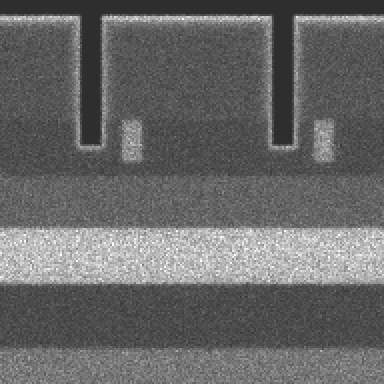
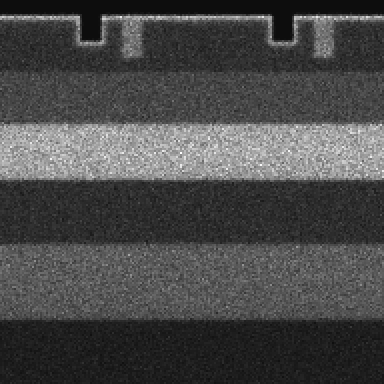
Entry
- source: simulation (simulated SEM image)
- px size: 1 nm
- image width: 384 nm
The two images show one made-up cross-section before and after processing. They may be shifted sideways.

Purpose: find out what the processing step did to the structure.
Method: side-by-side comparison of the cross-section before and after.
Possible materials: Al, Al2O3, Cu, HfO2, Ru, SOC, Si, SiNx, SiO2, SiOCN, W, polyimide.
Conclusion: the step removed SOC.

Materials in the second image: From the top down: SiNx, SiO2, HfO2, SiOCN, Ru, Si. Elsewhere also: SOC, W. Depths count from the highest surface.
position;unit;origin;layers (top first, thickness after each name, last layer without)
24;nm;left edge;SiNx 56, SiO2 52, HfO2 56, SiOCN 64, Ru 76, Si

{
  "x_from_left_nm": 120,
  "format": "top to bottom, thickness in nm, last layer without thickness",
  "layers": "SiNx 56, SiO2 52, HfO2 56, SiOCN 64, Ru 76, Si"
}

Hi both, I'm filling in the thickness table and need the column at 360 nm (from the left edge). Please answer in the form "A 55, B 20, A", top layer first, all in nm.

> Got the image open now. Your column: SiNx 56, SiO2 52, HfO2 56, SiOCN 64, Ru 76, Si